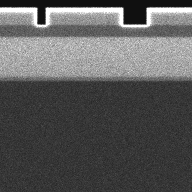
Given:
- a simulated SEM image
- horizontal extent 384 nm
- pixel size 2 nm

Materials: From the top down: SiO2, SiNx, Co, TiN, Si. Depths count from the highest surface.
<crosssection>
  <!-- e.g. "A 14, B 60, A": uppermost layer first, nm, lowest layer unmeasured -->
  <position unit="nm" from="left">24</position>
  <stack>SiO2 34, SiNx 24, Co 80, TiN 8, Si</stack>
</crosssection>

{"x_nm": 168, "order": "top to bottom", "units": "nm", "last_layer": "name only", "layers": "SiO2 34, SiNx 24, Co 80, TiN 8, Si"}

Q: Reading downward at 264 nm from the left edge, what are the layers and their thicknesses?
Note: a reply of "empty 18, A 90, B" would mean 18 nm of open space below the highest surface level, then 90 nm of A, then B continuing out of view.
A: empty 34, SiNx 24, Co 80, TiN 8, Si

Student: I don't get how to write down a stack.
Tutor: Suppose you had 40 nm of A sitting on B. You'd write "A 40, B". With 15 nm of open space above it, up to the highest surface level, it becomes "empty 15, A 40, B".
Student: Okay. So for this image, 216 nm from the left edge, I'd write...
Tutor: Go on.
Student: SiO2 34, SiNx 24, Co 80, TiN 8, Si